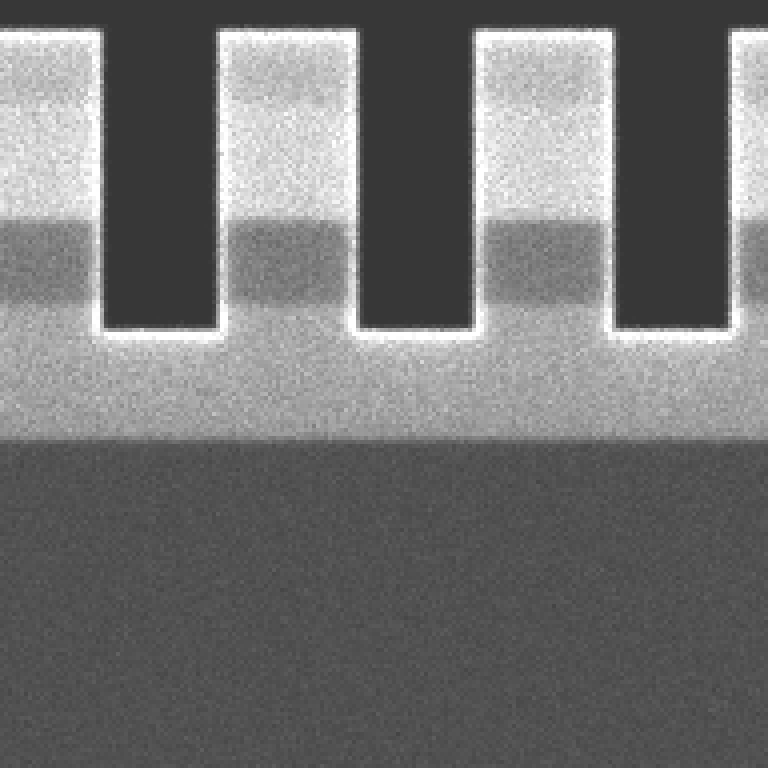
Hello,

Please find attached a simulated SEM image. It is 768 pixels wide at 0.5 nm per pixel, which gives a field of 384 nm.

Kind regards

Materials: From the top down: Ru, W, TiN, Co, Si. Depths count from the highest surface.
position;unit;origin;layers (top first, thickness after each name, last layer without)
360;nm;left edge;empty 150, Co 54, Si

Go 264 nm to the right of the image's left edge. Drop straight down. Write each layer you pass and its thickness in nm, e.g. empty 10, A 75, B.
Ru 36, W 58, TiN 42, Co 68, Si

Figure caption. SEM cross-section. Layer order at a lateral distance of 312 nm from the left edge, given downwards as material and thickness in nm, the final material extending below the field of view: empty 150, Co 54, Si